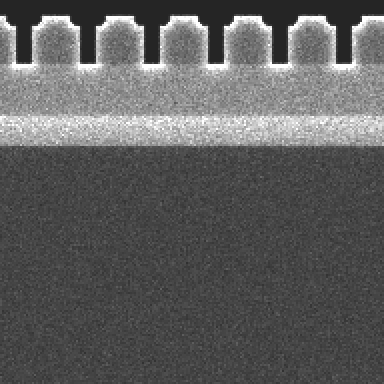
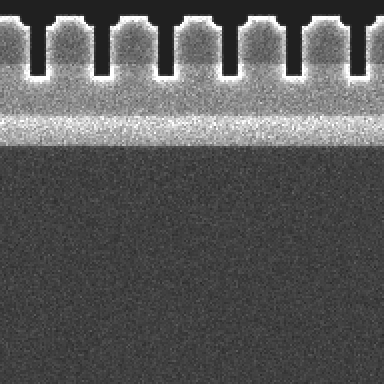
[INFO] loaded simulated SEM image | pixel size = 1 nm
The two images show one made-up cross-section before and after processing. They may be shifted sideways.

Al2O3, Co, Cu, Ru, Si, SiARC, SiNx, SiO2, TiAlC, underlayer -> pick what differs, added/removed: SiO2 removed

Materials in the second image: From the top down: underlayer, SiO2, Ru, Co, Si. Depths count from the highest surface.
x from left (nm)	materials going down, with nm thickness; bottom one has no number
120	underlayer 48, SiO2 52, Ru 12, Co 18, Si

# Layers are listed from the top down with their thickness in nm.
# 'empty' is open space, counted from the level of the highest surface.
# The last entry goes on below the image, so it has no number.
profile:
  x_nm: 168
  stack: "empty 60, SiO2 40, Ru 12, Co 18, Si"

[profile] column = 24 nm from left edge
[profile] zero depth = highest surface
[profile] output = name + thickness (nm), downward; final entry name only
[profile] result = empty 10, underlayer 38, SiO2 52, Ru 12, Co 18, Si